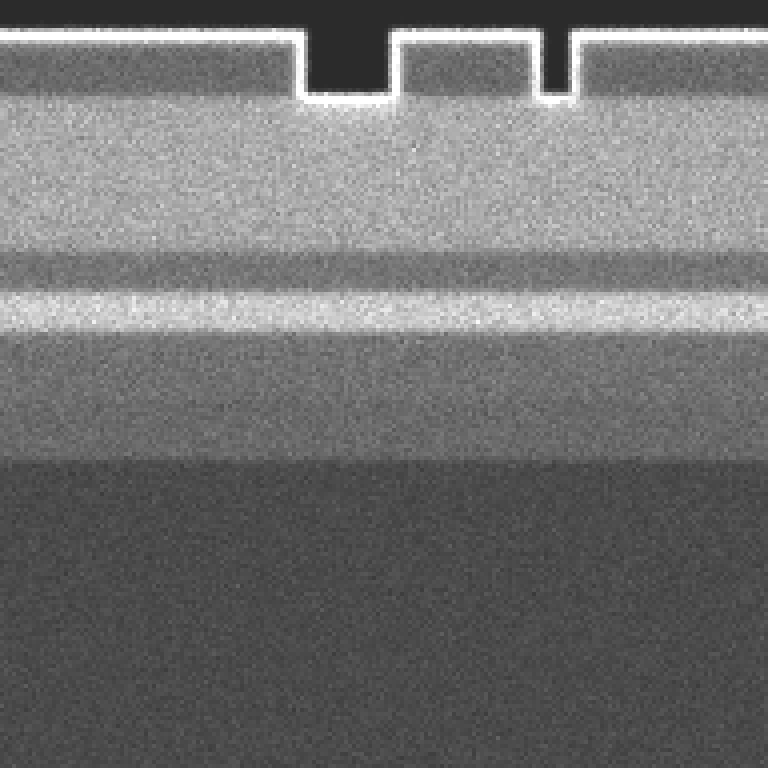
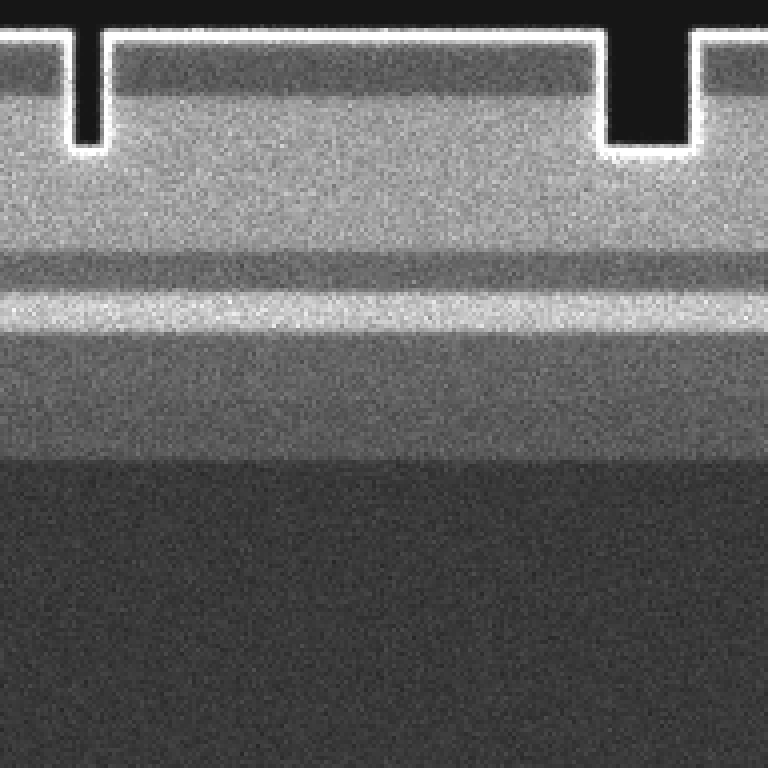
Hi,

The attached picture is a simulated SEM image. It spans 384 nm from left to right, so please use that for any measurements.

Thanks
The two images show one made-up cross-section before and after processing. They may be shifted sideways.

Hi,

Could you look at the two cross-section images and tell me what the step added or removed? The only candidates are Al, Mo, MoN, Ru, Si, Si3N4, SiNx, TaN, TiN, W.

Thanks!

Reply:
removed Ru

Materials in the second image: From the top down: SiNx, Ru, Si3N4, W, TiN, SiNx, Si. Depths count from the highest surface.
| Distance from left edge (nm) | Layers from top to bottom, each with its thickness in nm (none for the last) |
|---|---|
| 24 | SiNx 32, Ru 78, Si3N4 20, W 20, TiN 34, SiNx 30, Si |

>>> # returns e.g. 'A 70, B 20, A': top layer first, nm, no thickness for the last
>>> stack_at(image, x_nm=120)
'SiNx 32, Ru 78, Si3N4 20, W 20, TiN 34, SiNx 30, Si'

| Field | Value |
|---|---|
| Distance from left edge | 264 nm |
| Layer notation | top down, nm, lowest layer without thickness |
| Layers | SiNx 32, Ru 78, Si3N4 20, W 20, TiN 34, SiNx 30, Si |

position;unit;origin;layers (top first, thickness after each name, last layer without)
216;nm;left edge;SiNx 32, Ru 78, Si3N4 20, W 20, TiN 34, SiNx 30, Si